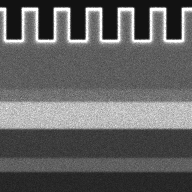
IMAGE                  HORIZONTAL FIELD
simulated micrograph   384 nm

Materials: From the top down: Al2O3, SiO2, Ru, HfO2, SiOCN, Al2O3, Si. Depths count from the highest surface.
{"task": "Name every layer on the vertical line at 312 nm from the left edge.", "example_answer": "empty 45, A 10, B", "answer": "Al2O3 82, SiO2 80, Ru 26, HfO2 54, SiOCN 58, Al2O3 28, Si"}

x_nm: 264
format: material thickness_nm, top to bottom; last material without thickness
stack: Al2O3 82, SiO2 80, Ru 26, HfO2 54, SiOCN 58, Al2O3 28, Si